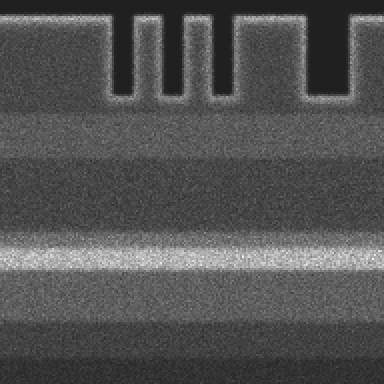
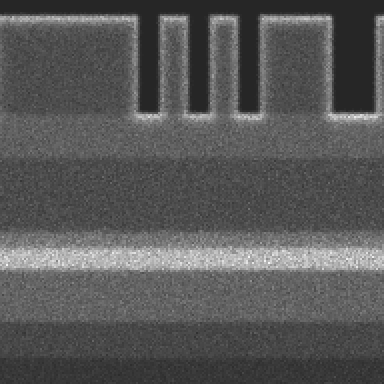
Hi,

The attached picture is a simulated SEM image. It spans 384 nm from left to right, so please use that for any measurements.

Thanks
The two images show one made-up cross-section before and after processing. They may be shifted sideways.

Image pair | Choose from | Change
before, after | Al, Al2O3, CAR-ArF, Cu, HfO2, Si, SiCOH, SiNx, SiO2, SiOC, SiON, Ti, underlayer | underlayer (removed)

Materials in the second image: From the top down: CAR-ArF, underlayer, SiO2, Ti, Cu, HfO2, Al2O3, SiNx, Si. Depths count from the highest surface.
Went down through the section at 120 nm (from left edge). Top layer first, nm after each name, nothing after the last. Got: CAR-ArF 80, underlayer 18, SiO2 44, Ti 74, Cu 16, HfO2 22, Al2O3 52, SiNx 36, Si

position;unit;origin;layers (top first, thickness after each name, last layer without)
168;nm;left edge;CAR-ArF 80, underlayer 18, SiO2 44, Ti 74, Cu 16, HfO2 22, Al2O3 52, SiNx 36, Si